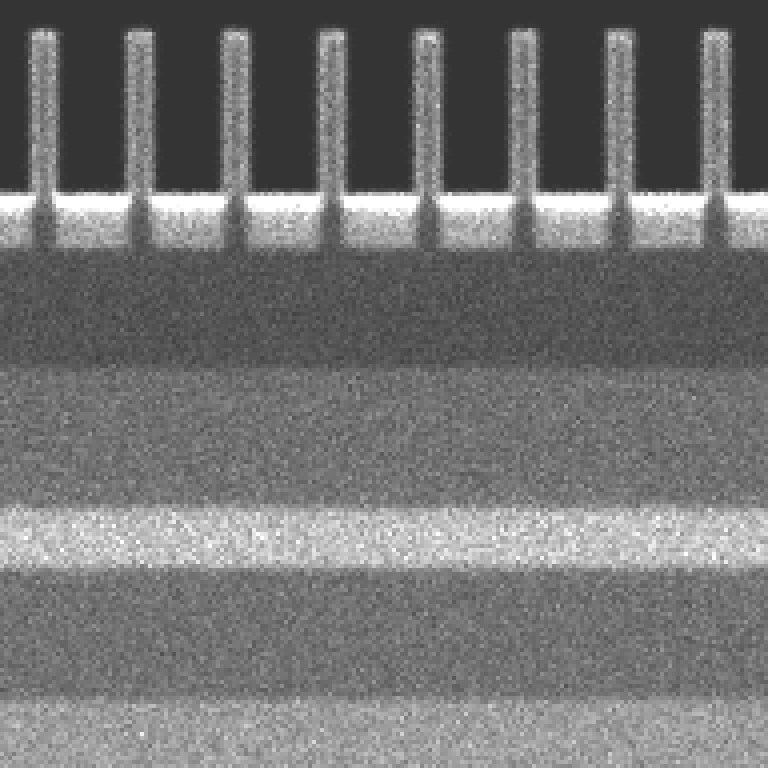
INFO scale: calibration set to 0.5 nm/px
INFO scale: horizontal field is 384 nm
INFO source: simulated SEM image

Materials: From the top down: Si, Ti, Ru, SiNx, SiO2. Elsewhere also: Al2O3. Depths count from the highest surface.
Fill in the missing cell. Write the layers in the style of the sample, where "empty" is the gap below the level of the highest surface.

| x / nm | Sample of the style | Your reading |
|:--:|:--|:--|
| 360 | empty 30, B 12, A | Si 168, Ti 70, Ru 30, SiNx 66, SiO2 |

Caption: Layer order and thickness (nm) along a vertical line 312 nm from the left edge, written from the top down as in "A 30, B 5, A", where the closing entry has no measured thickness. Si 168, Ti 70, Ru 30, SiNx 66, SiO2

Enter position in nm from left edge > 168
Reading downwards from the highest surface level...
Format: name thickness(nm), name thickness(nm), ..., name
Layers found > Si 168, Ti 70, Ru 30, SiNx 66, SiO2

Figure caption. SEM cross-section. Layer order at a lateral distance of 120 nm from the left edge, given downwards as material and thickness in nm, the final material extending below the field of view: Si 168, Ti 70, Ru 30, SiNx 66, SiO2